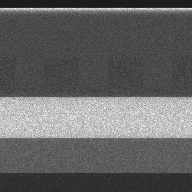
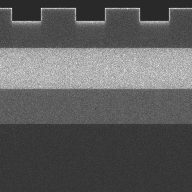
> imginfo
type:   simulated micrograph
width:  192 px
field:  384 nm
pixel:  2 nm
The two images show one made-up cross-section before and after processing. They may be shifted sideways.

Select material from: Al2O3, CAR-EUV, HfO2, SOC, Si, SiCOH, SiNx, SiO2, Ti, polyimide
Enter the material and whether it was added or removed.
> SOC / removed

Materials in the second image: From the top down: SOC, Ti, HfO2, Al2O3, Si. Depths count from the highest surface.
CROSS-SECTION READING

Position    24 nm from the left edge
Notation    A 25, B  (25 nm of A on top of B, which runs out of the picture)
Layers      empty 26, SOC 36, Ti 18, HfO2 82, Al2O3 70, Si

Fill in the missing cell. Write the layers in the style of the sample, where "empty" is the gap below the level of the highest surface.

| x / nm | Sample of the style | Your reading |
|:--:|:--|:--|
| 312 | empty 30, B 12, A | empty 26, SOC 36, Ti 18, HfO2 82, Al2O3 70, Si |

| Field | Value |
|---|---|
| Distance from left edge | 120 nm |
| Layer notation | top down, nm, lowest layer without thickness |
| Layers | Ti 80, HfO2 82, Al2O3 70, Si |